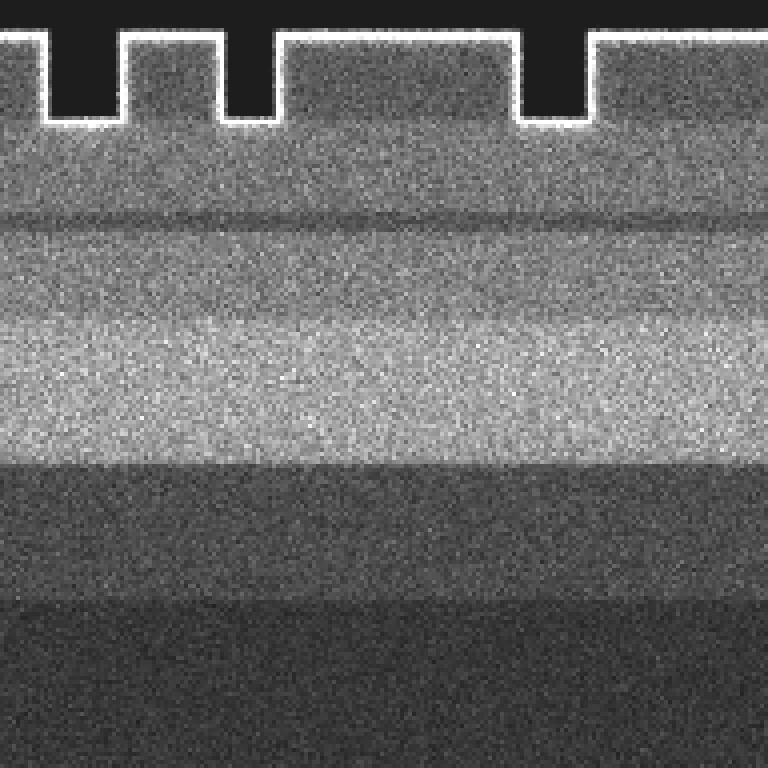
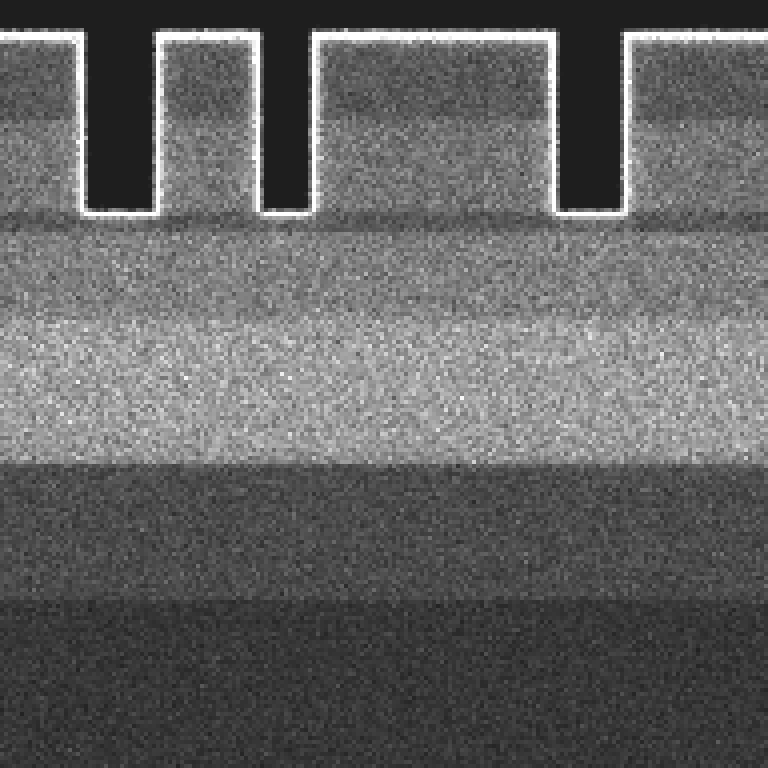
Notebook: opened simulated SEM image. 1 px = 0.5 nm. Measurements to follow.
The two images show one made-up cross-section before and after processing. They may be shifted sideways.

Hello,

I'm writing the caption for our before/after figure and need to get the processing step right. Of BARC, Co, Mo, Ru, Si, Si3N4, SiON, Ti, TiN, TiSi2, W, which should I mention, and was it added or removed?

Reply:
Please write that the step removed Co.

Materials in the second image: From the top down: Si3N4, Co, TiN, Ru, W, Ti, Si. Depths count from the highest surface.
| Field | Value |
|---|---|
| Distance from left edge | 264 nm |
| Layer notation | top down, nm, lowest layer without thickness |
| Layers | Si3N4 44, Co 46, TiN 10, Ru 44, W 72, Ti 68, Si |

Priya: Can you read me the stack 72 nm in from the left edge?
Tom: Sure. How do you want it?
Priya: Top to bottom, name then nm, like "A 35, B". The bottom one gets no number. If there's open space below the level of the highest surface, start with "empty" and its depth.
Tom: empty 90, TiN 10, Ru 44, W 72, Ti 68, Si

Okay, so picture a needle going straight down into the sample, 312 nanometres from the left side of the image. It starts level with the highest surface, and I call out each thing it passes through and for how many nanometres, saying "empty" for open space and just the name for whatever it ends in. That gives Si3N4 44, Co 46, TiN 10, Ru 44, W 72, Ti 68, Si